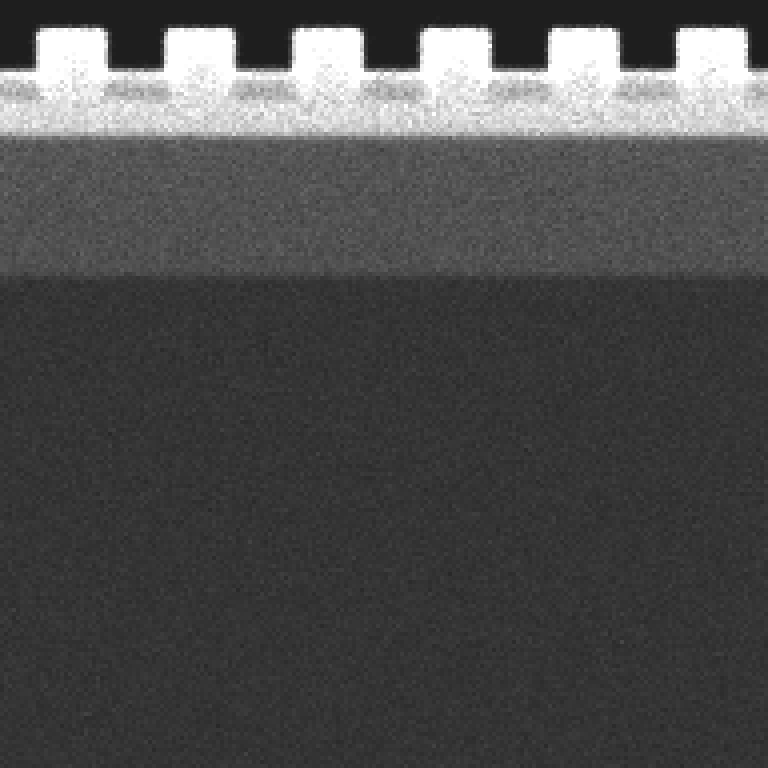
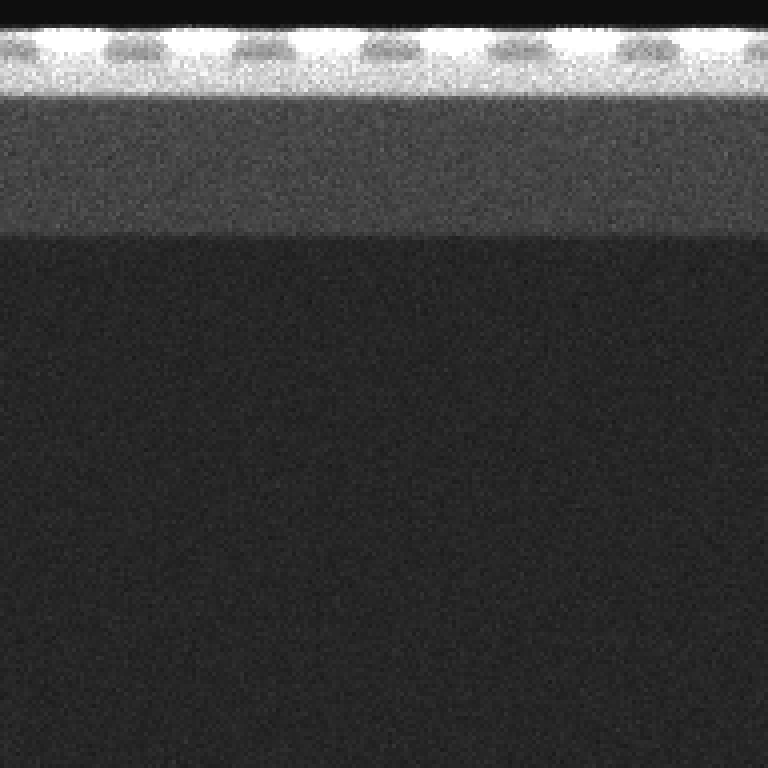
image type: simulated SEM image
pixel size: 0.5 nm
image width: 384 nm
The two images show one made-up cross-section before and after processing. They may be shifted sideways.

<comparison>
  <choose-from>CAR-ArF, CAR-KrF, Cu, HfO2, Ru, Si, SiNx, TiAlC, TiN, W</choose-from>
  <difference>HfO2 removed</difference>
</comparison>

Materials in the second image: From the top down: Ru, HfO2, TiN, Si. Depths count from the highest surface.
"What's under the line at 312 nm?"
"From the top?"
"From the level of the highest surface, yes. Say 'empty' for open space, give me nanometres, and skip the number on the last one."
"Ru 14, HfO2 18, TiN 70, Si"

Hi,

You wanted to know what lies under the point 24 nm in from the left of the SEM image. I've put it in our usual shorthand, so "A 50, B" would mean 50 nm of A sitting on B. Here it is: HfO2 32, TiN 70, Si